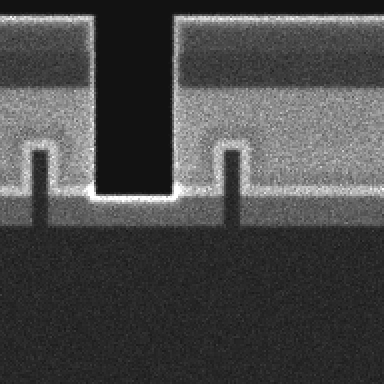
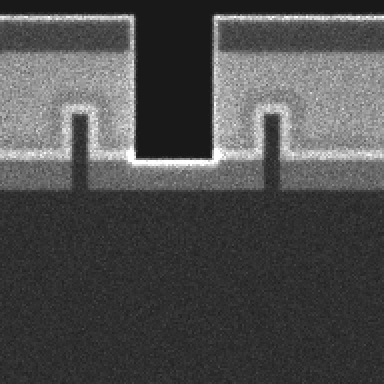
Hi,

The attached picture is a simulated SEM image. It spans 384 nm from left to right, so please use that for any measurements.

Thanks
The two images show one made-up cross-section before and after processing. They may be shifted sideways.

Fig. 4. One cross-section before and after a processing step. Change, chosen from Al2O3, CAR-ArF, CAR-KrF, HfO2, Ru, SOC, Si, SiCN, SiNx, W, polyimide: SOC removed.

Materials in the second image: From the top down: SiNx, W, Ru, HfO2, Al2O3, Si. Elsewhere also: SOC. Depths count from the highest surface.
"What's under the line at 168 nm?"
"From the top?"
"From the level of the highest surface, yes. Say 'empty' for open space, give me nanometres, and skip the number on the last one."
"empty 144, Al2O3 30, Si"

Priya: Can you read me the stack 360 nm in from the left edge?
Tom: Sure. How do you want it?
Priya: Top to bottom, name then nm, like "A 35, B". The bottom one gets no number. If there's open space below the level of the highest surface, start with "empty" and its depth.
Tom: SiNx 36, W 84, Ru 14, HfO2 10, Al2O3 30, Si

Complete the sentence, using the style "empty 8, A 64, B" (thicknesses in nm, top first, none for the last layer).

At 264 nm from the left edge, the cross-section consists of SiNx 36, W 38, Ru 14, HfO2 10, Si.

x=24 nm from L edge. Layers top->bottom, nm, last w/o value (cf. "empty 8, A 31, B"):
SiNx 36, W 84, Ru 14, HfO2 10, Al2O3 30, Si